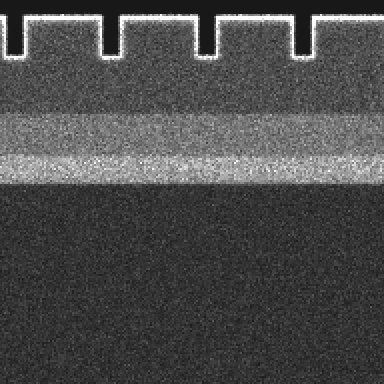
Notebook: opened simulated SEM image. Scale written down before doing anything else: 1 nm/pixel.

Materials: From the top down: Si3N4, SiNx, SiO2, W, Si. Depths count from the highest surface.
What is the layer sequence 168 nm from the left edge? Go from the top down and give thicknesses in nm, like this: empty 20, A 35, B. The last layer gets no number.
Si3N4 10, SiNx 88, SiO2 42, W 28, Si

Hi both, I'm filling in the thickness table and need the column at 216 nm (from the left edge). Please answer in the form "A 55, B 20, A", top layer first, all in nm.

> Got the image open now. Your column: Si3N4 10, SiNx 88, SiO2 42, W 28, Si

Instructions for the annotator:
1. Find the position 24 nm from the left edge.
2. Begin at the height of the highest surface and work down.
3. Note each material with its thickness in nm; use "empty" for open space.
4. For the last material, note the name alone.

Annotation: Si3N4 10, SiNx 88, SiO2 42, W 28, Si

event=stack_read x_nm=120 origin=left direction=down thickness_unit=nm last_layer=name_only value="Si3N4 10, SiNx 88, SiO2 42, W 28, Si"